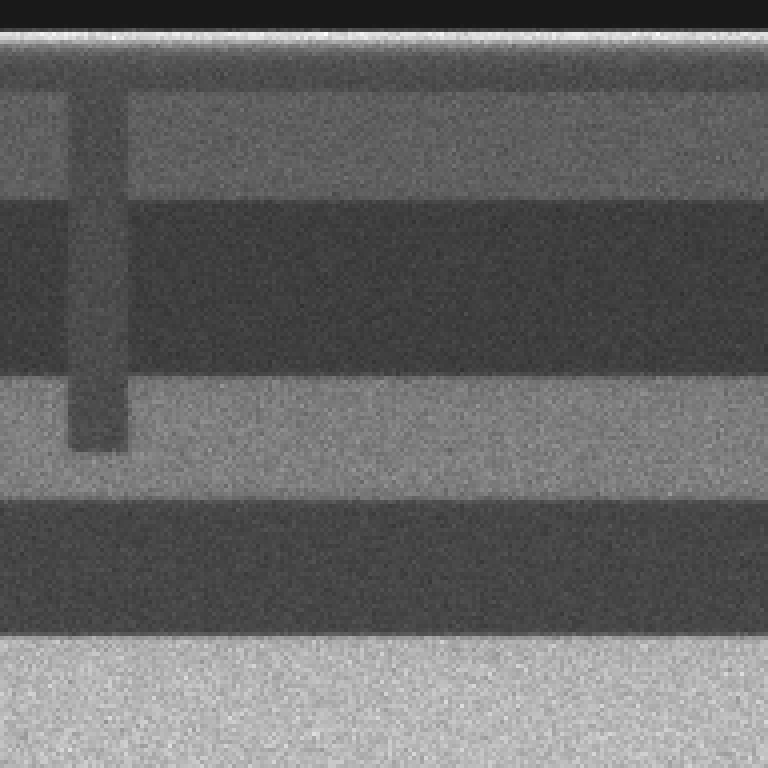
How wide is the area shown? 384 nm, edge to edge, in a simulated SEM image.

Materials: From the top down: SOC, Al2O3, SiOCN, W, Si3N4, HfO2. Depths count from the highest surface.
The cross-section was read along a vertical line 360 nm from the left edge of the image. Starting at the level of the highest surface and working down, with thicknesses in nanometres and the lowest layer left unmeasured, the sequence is SOC 30, Al2O3 54, SiOCN 88, W 62, Si3N4 68, HfO2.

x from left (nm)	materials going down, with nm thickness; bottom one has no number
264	SOC 30, Al2O3 54, SiOCN 88, W 62, Si3N4 68, HfO2